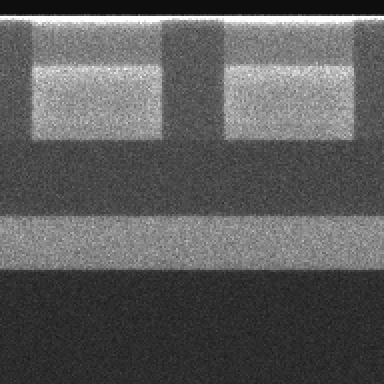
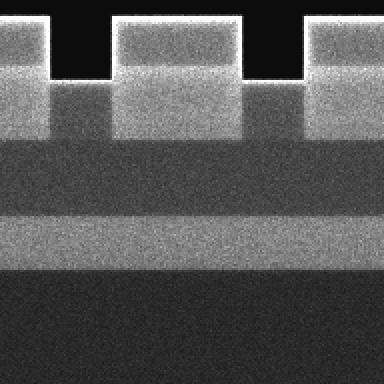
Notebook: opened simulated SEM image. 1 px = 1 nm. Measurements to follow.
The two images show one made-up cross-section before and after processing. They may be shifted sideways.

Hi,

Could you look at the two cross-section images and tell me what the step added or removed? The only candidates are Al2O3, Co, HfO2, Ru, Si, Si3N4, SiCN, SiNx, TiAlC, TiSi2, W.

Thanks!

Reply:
removed Si3N4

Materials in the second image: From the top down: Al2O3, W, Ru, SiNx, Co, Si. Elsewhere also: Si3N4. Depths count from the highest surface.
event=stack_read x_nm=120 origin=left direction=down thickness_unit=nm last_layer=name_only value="Al2O3 50, W 58, Ru 16, SiNx 76, Co 54, Si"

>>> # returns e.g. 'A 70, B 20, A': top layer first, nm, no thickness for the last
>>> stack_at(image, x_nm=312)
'Al2O3 50, W 58, Ru 16, SiNx 76, Co 54, Si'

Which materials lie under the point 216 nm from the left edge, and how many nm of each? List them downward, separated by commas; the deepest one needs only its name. Al2O3 50, W 58, Ru 16, SiNx 76, Co 54, Si